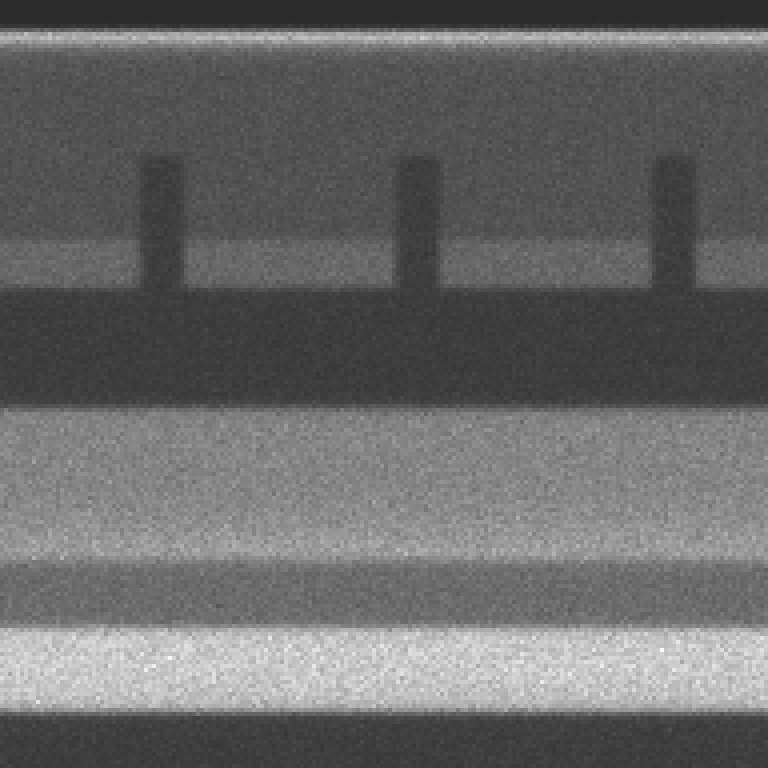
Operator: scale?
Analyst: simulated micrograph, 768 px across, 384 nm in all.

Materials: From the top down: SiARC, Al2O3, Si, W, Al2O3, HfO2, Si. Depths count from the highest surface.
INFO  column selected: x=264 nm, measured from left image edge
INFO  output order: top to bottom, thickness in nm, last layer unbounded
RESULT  SiARC 104, Al2O3 24, Si 60, W 76, Al2O3 34, HfO2 42, Si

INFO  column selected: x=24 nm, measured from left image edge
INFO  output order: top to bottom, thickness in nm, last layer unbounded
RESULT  SiARC 104, Al2O3 24, Si 60, W 76, Al2O3 34, HfO2 42, Si